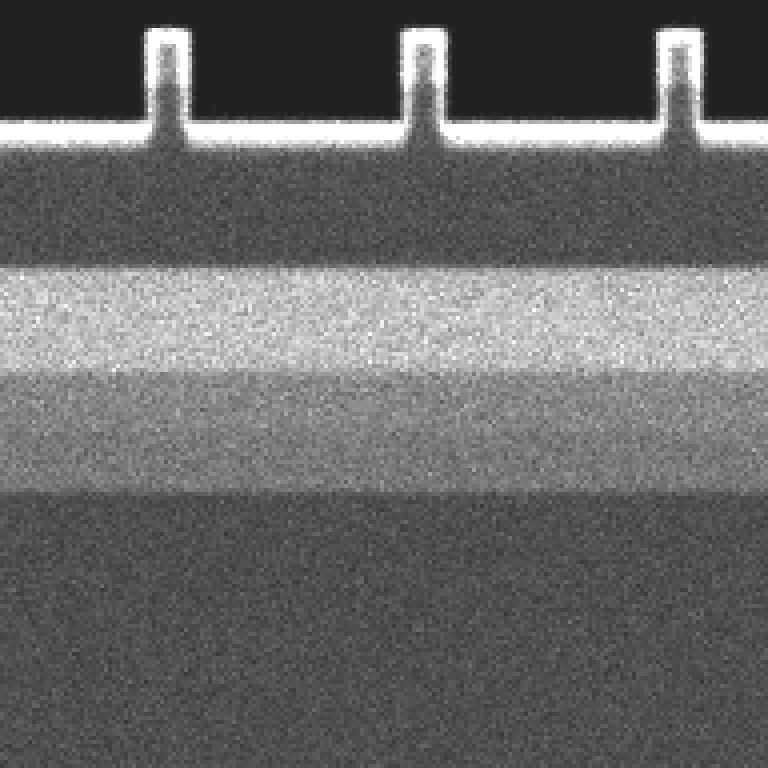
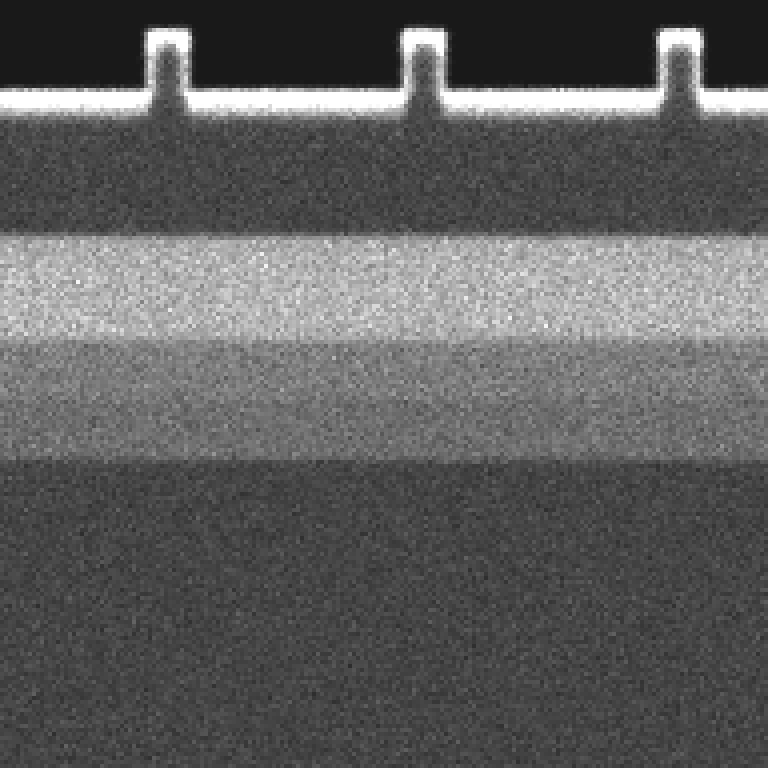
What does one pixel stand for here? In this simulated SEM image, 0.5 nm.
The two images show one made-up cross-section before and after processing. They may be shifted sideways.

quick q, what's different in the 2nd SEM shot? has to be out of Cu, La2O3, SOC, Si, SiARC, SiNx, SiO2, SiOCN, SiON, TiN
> SiOCN removed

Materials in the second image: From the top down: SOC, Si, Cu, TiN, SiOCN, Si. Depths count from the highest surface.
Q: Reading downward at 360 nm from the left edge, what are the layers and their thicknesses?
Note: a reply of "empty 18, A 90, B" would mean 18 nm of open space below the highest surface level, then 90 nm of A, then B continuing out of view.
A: empty 30, SOC 12, Si 60, Cu 52, TiN 30, SiOCN 30, Si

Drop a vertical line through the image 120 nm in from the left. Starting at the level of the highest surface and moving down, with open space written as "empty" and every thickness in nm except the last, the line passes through empty 30, SOC 12, Si 60, Cu 52, TiN 30, SiOCN 30, Si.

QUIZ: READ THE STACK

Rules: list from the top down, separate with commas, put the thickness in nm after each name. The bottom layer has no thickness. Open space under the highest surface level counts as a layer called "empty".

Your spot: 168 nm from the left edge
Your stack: empty 30, SOC 12, Si 60, Cu 52, TiN 30, SiOCN 30, Si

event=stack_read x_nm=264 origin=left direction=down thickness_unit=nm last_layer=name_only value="empty 30, SOC 12, Si 60, Cu 52, TiN 30, SiOCN 30, Si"